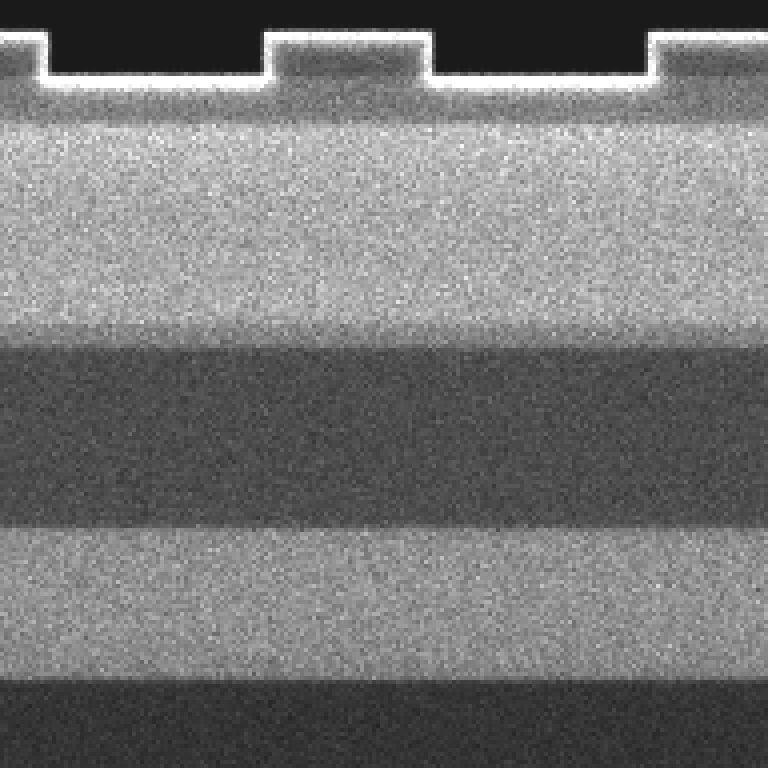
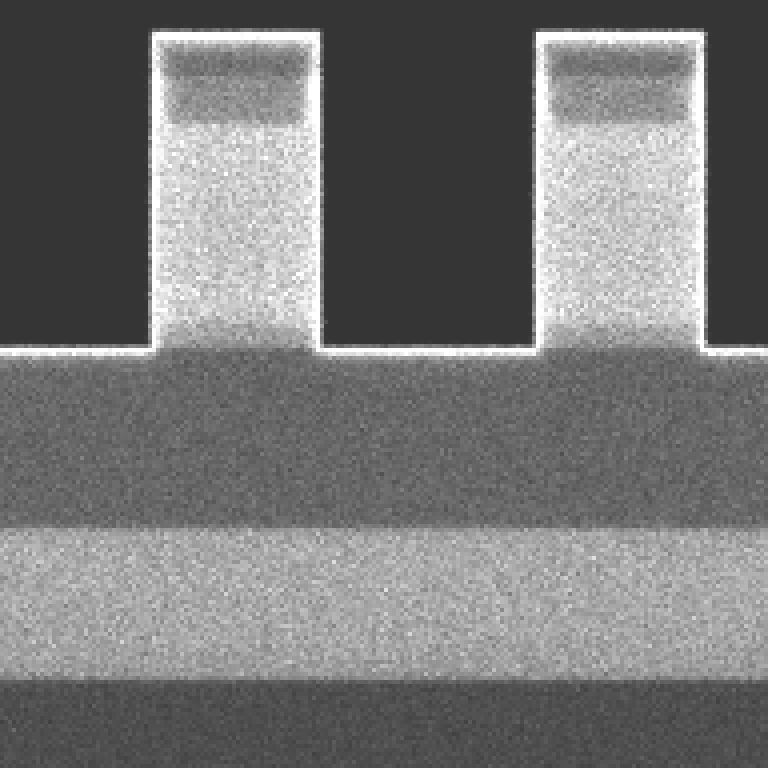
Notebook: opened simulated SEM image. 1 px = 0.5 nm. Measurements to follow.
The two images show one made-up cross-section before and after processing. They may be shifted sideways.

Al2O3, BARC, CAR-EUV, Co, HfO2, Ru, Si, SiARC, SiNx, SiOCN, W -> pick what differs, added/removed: Al2O3 and Co and W removed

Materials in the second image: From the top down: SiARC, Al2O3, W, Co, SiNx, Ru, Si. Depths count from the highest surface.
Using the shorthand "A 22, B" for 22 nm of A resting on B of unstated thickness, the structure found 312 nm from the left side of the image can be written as SiARC 22, Al2O3 24, W 100, Co 12, SiNx 90, Ru 76, Si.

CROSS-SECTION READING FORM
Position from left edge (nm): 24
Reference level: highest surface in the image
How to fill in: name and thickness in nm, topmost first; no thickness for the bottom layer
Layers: empty 158, SiNx 90, Ru 76, Si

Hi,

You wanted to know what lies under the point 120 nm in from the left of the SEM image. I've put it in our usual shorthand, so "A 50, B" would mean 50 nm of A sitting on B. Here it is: SiARC 22, Al2O3 24, W 100, Co 12, SiNx 90, Ru 76, Si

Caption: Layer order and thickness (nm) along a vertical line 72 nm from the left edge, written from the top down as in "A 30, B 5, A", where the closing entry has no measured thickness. empty 158, SiNx 90, Ru 76, Si